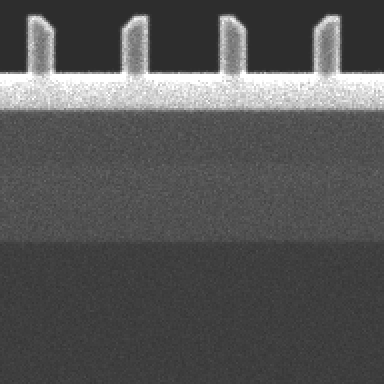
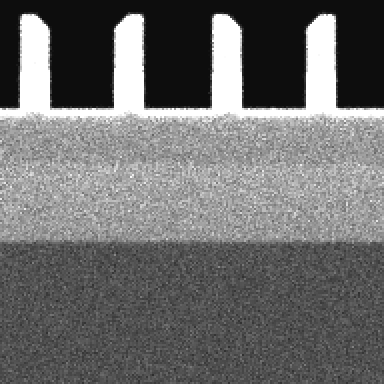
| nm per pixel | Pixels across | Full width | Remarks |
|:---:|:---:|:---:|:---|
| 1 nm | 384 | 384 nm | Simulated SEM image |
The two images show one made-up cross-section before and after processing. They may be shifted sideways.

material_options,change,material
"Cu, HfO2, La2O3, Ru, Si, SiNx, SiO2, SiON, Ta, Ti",removed,HfO2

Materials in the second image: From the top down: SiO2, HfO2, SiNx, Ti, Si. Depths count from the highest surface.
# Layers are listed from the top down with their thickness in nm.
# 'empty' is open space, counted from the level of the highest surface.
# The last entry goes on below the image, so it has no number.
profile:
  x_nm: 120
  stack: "empty 8, SiO2 50, HfO2 36, SiNx 54, Ti 78, Si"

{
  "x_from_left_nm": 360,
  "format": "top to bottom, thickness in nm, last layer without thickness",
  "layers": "empty 94, SiNx 54, Ti 78, Si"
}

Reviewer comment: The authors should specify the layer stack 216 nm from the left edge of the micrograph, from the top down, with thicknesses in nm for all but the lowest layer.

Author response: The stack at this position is SiO2 58, HfO2 36, SiNx 54, Ti 78, Si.